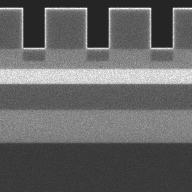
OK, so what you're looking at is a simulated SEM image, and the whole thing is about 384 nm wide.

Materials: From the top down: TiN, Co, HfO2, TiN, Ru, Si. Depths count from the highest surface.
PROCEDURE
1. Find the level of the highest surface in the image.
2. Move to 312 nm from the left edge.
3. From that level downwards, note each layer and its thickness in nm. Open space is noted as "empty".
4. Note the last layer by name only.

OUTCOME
empty 80, TiN 26, Co 16, HfO2 30, TiN 52, Ru 66, Si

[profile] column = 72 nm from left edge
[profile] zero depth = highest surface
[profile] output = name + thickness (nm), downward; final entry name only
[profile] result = empty 80, TiN 26, Co 16, HfO2 30, TiN 52, Ru 66, Si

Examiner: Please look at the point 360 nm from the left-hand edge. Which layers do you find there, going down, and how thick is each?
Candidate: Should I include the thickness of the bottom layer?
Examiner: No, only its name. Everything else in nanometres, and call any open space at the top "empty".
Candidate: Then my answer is TiN 82, Co 40, HfO2 30, TiN 52, Ru 66, Si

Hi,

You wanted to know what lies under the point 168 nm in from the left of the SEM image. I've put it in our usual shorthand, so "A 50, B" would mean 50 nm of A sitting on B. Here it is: TiN 82, Co 40, HfO2 30, TiN 52, Ru 66, Si